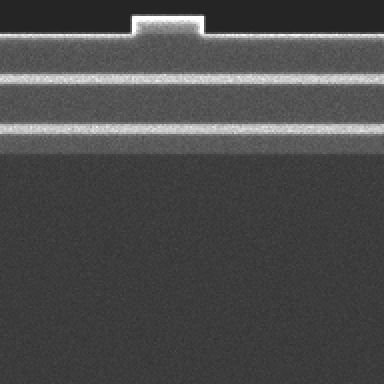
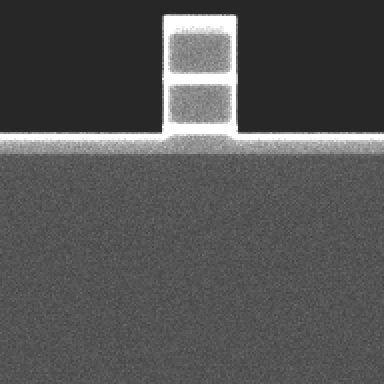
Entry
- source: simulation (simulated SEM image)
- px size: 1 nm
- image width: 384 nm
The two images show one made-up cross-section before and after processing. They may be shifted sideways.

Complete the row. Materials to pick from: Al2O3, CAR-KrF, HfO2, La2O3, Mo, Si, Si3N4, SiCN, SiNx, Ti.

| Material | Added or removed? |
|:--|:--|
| HfO2 and SiNx | removed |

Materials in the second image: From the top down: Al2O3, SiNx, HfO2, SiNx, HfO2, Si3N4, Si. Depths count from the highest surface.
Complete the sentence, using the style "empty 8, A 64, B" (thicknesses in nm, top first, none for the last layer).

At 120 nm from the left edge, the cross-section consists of empty 118, Si3N4 20, Si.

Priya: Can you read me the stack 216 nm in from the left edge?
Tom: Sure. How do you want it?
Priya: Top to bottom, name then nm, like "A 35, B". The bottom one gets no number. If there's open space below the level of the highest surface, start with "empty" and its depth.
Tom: Al2O3 18, SiNx 40, HfO2 10, SiNx 40, HfO2 10, Si3N4 20, Si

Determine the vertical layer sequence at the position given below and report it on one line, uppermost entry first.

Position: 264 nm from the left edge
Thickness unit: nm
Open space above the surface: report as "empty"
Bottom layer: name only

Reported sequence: empty 118, Si3N4 20, Si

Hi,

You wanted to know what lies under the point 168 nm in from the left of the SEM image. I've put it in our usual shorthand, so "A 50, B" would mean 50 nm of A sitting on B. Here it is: Al2O3 18, SiNx 40, HfO2 10, SiNx 40, HfO2 10, Si3N4 20, Si